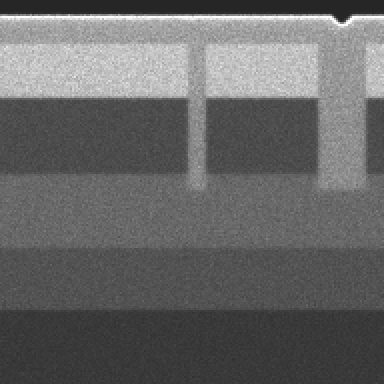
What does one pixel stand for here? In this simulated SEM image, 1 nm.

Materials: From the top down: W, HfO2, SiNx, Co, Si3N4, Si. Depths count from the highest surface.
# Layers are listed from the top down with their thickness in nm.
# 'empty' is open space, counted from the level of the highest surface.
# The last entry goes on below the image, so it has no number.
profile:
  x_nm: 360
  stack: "W 174, Co 58, Si3N4 62, Si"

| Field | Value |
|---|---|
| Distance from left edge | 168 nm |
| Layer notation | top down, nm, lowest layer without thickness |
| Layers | W 28, HfO2 54, SiNx 76, Co 74, Si3N4 62, Si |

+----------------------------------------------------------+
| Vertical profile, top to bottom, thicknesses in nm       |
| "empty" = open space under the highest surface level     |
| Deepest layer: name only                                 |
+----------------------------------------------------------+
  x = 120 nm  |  W 28, HfO2 54, SiNx 76, Co 74, Si3N4 62, Si